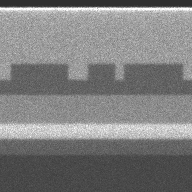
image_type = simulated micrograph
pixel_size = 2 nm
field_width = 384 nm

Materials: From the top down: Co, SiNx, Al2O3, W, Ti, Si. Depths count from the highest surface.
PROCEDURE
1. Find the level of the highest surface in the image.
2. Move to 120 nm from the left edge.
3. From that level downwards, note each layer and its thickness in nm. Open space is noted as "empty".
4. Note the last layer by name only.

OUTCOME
Co 112, SiNx 62, Al2O3 58, W 30, Ti 32, Si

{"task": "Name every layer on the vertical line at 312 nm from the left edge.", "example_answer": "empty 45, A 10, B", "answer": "Co 112, SiNx 62, Al2O3 58, W 30, Ti 32, Si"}